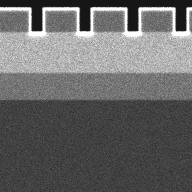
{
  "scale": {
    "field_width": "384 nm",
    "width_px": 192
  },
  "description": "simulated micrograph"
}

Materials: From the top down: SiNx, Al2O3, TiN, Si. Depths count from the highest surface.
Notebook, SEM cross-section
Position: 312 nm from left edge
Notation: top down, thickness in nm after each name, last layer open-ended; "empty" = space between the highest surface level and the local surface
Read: SiNx 48, Al2O3 82, TiN 54, Si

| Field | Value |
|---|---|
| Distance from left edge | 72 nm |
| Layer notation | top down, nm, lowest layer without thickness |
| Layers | empty 48, Al2O3 82, TiN 54, Si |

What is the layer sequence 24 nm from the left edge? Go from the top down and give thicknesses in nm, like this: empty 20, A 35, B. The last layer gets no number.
SiNx 48, Al2O3 82, TiN 54, Si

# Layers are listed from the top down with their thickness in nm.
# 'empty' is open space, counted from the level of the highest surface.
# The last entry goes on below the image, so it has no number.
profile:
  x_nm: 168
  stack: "empty 48, Al2O3 82, TiN 54, Si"